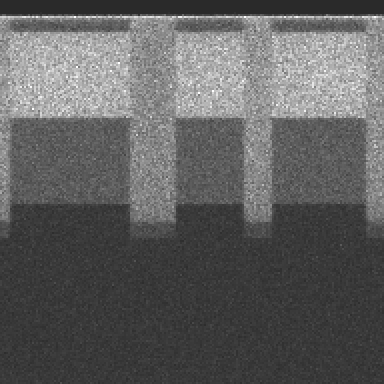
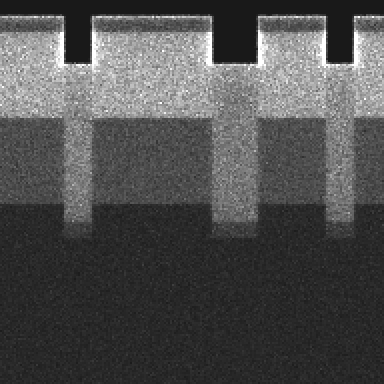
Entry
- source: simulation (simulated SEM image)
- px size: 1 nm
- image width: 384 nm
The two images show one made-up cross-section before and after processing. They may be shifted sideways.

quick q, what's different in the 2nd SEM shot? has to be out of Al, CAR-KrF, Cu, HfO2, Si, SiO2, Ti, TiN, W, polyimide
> W removed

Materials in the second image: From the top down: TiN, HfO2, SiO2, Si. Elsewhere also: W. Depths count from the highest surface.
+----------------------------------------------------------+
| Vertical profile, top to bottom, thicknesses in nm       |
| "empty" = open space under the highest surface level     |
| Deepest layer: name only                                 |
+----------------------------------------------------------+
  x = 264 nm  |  TiN 16, HfO2 86, SiO2 86, Si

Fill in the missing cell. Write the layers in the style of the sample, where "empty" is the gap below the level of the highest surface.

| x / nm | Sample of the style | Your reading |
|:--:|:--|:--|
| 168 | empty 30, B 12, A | TiN 16, HfO2 86, SiO2 86, Si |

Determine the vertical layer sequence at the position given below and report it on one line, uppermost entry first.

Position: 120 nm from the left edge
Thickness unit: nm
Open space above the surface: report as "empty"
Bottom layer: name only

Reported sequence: TiN 16, HfO2 86, SiO2 86, Si